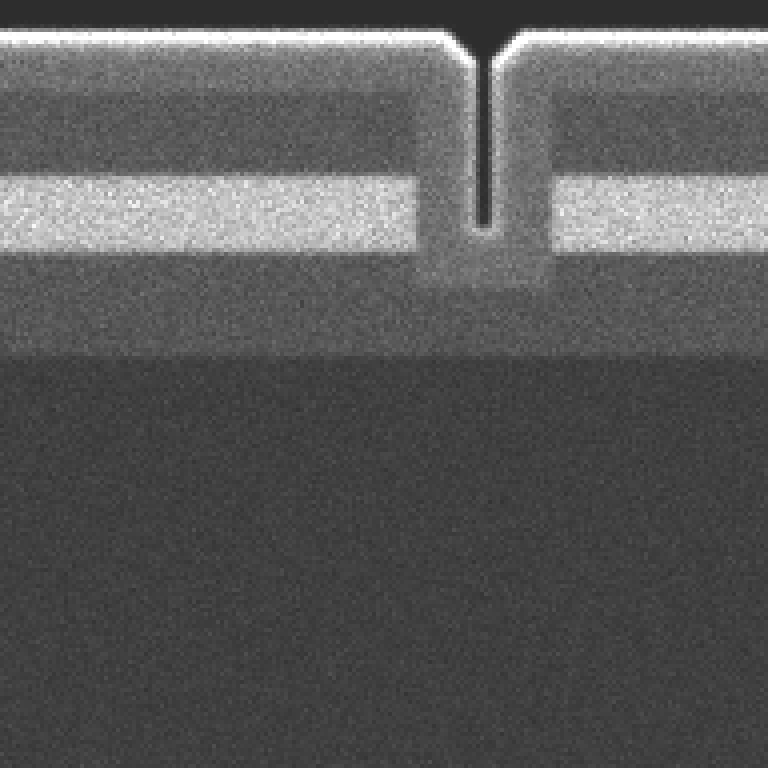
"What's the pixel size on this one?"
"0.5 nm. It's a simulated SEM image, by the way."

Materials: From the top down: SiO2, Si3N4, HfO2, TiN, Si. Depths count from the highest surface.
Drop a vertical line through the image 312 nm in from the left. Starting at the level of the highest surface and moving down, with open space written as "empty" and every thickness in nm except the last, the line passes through SiO2 30, Si3N4 42, HfO2 38, TiN 52, Si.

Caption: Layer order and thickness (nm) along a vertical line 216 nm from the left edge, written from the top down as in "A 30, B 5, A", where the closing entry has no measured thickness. SiO2 128, TiN 34, Si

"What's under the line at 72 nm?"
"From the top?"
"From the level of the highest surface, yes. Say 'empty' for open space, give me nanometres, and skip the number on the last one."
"SiO2 30, Si3N4 42, HfO2 38, TiN 52, Si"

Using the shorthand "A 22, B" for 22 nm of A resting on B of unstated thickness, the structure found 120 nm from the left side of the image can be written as SiO2 30, Si3N4 42, HfO2 38, TiN 52, Si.